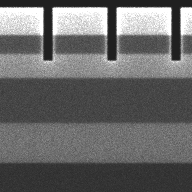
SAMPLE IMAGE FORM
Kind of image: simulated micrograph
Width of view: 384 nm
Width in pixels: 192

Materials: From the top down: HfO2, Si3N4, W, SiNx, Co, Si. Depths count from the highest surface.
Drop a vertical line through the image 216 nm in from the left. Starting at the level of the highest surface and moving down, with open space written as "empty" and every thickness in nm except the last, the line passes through empty 106, W 34, SiNx 90, Co 80, Si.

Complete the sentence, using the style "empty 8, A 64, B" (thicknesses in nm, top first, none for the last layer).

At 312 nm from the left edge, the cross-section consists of HfO2 54, Si3N4 38, W 48, SiNx 90, Co 80, Si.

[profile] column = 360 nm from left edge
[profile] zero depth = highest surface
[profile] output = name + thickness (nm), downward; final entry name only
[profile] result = empty 106, W 34, SiNx 90, Co 80, Si